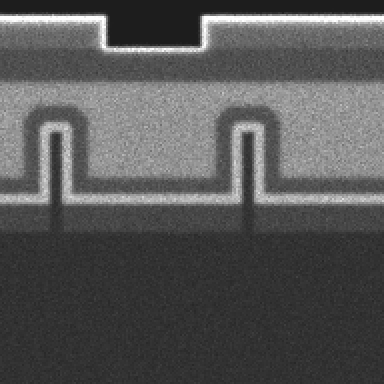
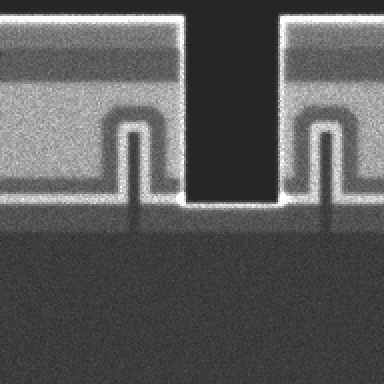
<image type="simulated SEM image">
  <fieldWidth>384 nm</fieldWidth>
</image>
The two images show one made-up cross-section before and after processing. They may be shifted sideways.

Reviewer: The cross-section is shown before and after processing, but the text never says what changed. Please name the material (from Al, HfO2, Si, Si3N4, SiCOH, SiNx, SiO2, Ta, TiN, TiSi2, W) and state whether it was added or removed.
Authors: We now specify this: HfO2 and Si3N4 and TiN and W, removed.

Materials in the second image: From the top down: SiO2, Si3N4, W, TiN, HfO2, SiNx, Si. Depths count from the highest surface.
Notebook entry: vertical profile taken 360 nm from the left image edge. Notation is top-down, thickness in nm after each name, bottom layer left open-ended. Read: SiO2 32, Si3N4 34, W 96, TiN 16, HfO2 10, SiNx 28, Si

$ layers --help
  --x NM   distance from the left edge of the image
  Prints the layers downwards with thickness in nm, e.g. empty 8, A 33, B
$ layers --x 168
SiO2 32, Si3N4 34, W 96, TiN 16, HfO2 10, SiNx 28, Si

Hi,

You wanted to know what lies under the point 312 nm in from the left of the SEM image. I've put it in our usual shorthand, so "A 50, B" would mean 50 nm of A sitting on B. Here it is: SiO2 32, Si3N4 34, W 24, TiN 18, HfO2 80, SiNx 28, Si